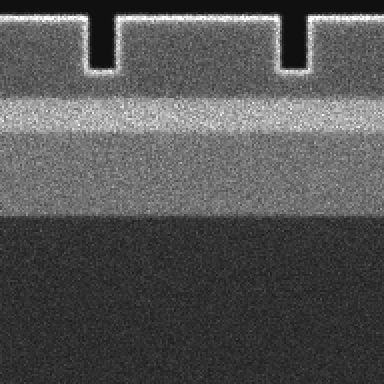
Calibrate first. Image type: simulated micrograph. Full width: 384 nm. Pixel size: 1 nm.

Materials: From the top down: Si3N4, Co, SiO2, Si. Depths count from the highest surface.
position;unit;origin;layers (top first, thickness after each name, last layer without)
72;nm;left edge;Si3N4 82, Co 34, SiO2 84, Si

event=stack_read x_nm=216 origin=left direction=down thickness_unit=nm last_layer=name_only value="Si3N4 82, Co 34, SiO2 84, Si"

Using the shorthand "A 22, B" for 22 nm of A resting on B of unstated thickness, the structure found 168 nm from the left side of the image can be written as Si3N4 82, Co 34, SiO2 84, Si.